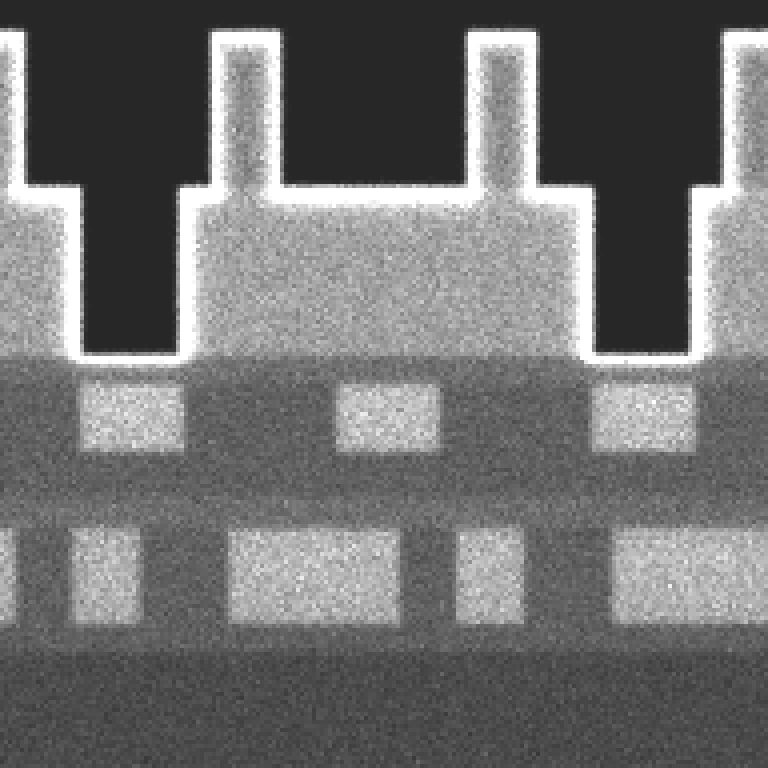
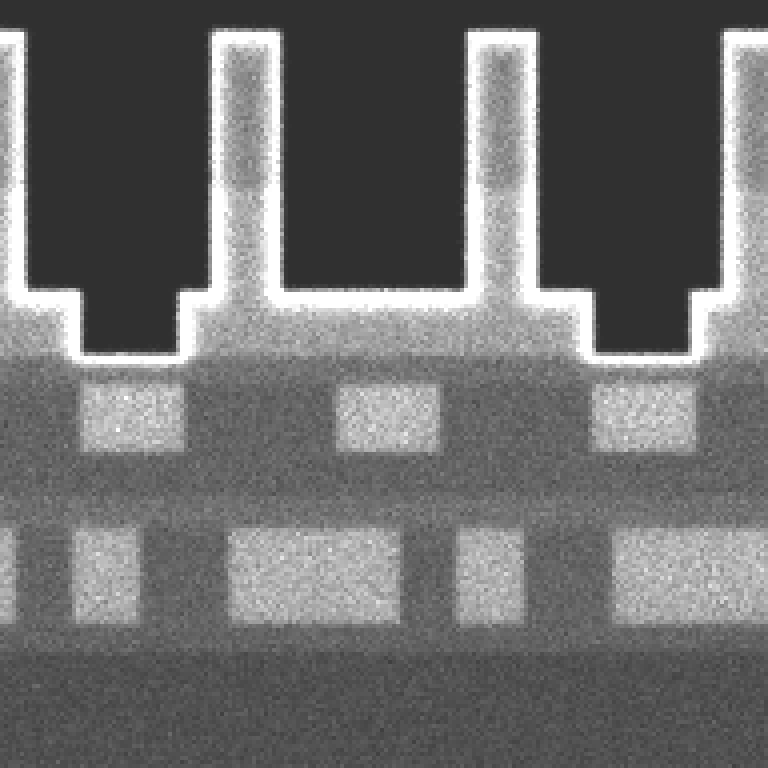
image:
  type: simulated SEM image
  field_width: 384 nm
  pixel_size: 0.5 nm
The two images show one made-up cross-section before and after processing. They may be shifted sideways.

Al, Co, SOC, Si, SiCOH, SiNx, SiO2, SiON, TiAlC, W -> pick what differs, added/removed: SiO2 removed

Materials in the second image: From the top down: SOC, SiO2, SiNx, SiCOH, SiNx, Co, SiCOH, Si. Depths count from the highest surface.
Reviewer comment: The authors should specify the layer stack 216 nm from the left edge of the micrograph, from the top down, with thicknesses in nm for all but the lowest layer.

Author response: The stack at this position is empty 130, SiO2 32, SiNx 14, Co 34, SiCOH 22, SiNx 16, SiCOH 62, Si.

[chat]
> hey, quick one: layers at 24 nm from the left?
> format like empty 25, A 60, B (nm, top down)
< empty 130, SiO2 32, SiNx 14, SiCOH 56, SiNx 16, SiCOH 62, Si